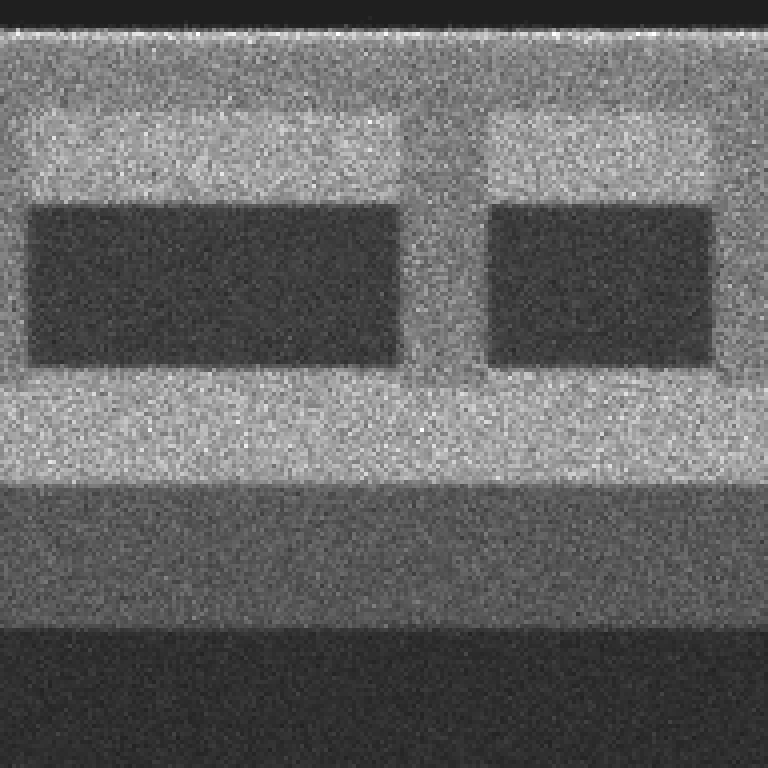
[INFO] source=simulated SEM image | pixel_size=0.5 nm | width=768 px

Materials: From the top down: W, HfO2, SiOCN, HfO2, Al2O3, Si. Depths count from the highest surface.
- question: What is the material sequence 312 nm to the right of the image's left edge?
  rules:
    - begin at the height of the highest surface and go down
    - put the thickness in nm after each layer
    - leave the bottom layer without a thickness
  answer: W 40, HfO2 46, SiOCN 82, HfO2 58, Al2O3 72, Si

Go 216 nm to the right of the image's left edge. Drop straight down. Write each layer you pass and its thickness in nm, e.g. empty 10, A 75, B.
W 178, HfO2 48, Al2O3 72, Si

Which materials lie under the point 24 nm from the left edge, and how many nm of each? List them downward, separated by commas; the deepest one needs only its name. W 40, HfO2 46, SiOCN 82, HfO2 58, Al2O3 72, Si